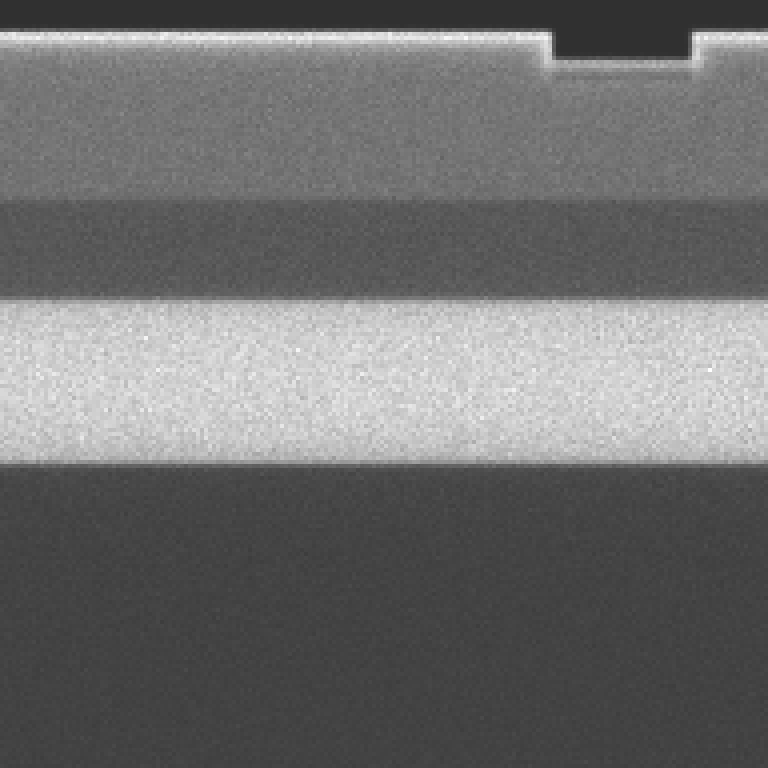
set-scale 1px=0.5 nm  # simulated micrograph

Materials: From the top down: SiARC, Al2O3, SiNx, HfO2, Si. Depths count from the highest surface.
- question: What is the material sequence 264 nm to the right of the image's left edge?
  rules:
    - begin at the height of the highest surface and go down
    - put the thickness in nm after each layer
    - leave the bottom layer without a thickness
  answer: Al2O3 84, SiNx 50, HfO2 82, Si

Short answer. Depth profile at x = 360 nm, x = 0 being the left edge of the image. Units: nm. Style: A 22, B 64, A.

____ Al2O3 84, SiNx 50, HfO2 82, Si